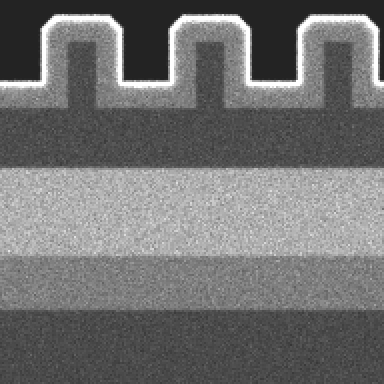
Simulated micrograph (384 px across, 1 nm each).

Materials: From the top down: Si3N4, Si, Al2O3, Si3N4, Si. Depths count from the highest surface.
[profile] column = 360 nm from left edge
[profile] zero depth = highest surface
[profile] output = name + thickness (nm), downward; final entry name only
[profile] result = Si3N4 92, Si 60, Al2O3 88, Si3N4 54, Si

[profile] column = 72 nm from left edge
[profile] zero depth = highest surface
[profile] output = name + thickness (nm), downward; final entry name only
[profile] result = Si3N4 26, Si 126, Al2O3 88, Si3N4 54, Si